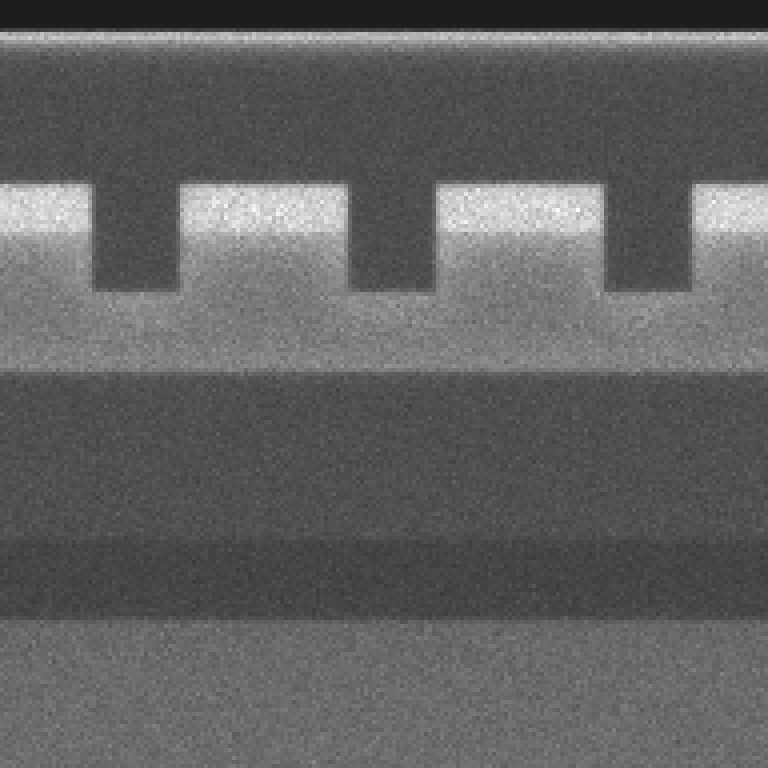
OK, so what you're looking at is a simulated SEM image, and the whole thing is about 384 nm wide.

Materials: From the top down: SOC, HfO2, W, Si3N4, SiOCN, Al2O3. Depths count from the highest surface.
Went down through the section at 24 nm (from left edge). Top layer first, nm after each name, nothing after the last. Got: SOC 76, HfO2 24, W 70, Si3N4 84, SiOCN 40, Al2O3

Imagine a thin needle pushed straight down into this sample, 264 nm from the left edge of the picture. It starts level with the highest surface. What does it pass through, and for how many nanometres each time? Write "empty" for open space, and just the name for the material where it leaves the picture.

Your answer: SOC 76, HfO2 24, W 70, Si3N4 84, SiOCN 40, Al2O3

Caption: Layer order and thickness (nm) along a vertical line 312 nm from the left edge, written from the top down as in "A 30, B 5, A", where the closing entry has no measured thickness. SOC 130, W 40, Si3N4 84, SiOCN 40, Al2O3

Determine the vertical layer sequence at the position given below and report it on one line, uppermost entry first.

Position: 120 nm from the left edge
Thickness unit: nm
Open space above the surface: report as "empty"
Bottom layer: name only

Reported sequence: SOC 76, HfO2 24, W 70, Si3N4 84, SiOCN 40, Al2O3